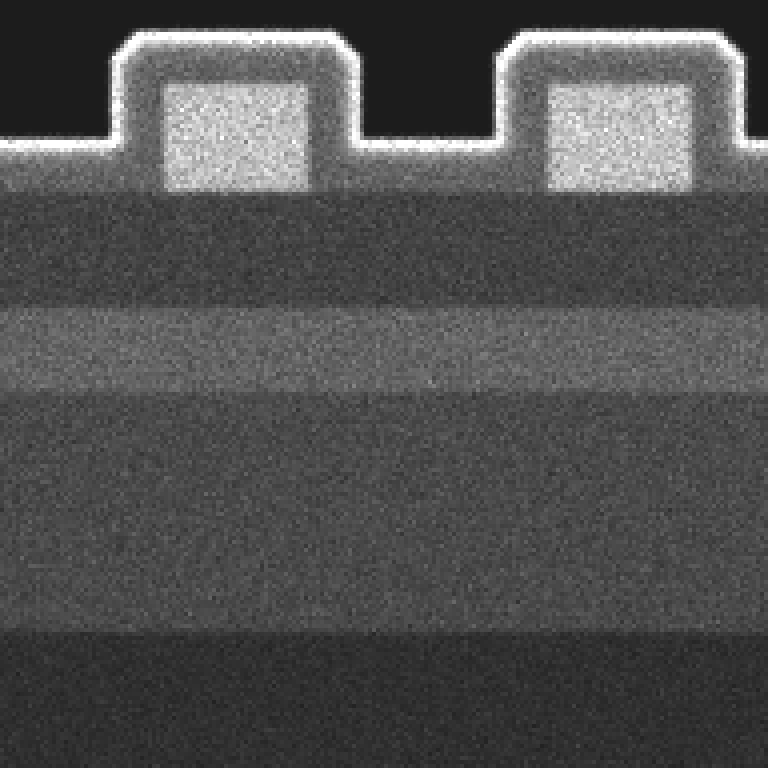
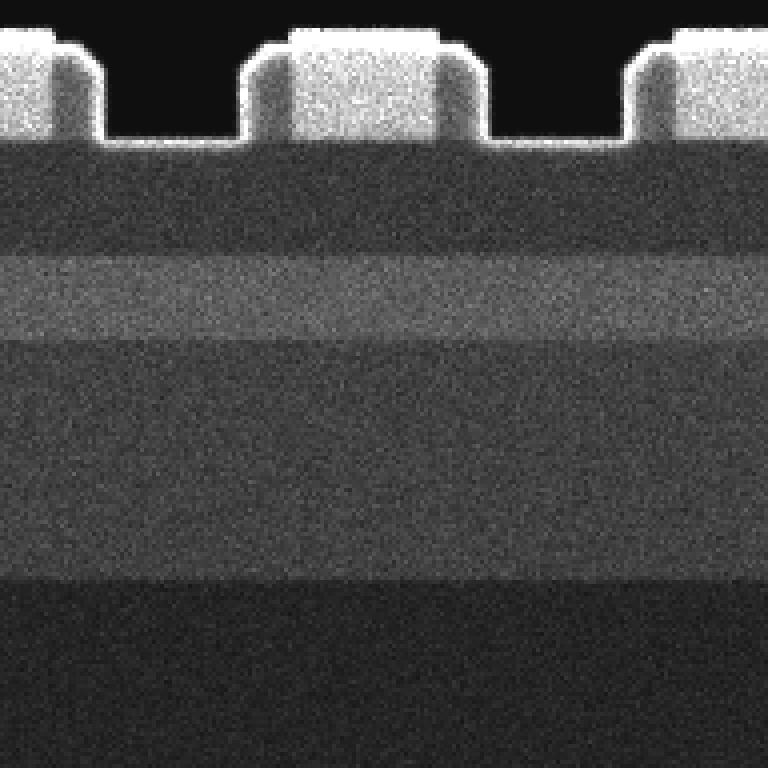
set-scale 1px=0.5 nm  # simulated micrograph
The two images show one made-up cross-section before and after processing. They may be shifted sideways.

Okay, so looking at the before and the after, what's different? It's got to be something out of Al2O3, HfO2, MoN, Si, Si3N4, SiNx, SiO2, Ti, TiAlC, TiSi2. SiO2, removed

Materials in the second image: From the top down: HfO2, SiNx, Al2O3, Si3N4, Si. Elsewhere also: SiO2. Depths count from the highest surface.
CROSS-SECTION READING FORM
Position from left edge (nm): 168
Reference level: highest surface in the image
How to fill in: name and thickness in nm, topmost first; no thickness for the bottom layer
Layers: HfO2 54, SiNx 58, Al2O3 42, Si3N4 120, Si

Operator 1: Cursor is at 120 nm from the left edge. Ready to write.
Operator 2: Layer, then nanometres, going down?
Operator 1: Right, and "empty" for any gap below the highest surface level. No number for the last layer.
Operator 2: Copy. empty 18, SiO2 36, SiNx 58, Al2O3 42, Si3N4 120, Si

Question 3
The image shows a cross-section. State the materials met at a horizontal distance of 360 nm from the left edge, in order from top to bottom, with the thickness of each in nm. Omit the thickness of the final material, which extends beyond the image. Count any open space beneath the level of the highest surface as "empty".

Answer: HfO2 54, SiNx 58, Al2O3 42, Si3N4 120, Si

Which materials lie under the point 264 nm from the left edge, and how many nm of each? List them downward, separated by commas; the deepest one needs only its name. empty 54, SiNx 58, Al2O3 42, Si3N4 120, Si